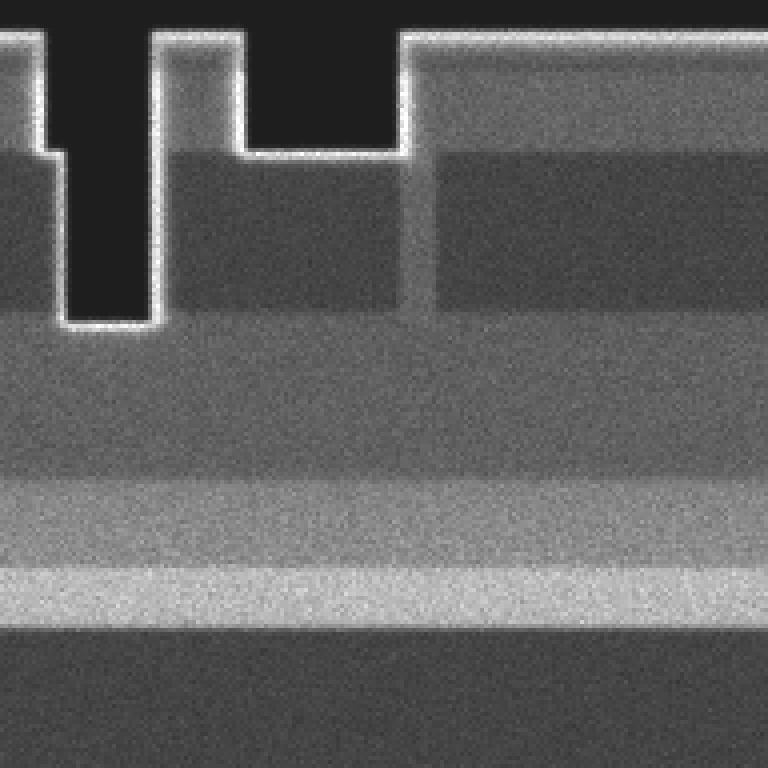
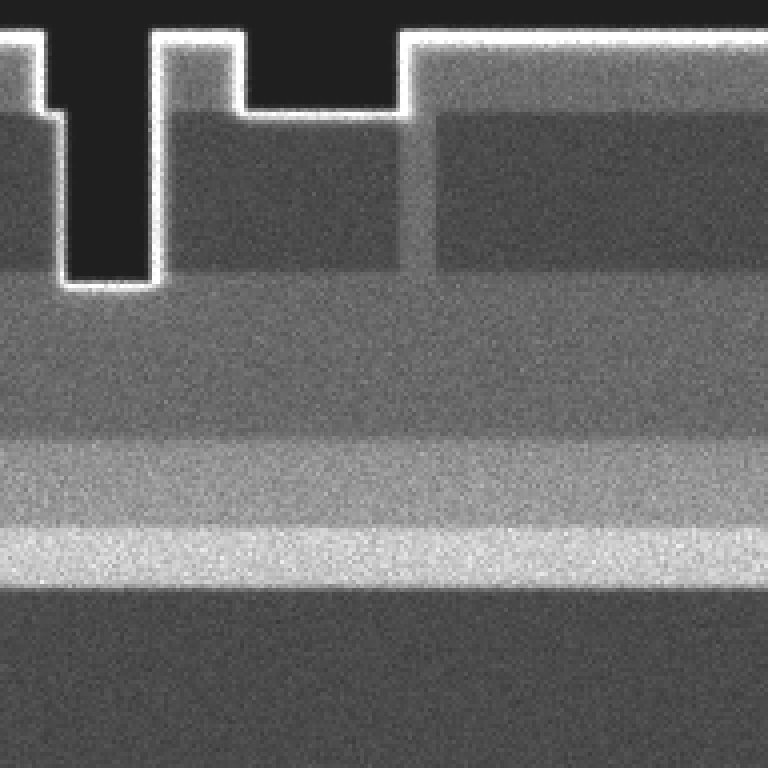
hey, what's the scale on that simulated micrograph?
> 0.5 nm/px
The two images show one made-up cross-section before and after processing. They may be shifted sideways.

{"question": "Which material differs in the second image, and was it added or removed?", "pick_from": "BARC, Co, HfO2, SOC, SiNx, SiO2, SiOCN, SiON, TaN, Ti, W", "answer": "SOC, removed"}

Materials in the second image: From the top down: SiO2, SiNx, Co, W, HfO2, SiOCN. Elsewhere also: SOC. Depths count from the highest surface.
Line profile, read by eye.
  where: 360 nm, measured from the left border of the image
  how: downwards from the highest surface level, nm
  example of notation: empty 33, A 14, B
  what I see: SiO2 40, SiNx 80, Co 84, W 44, HfO2 30, SiOCN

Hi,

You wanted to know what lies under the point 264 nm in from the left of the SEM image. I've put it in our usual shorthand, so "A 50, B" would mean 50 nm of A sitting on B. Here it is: SiO2 40, SiNx 80, Co 84, W 44, HfO2 30, SiOCN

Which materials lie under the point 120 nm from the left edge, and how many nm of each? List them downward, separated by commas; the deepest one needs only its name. SiO2 40, SiNx 80, Co 84, W 44, HfO2 30, SiOCN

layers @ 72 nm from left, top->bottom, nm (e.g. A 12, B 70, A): empty 126, Co 78, W 44, HfO2 30, SiOCN